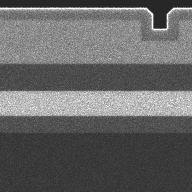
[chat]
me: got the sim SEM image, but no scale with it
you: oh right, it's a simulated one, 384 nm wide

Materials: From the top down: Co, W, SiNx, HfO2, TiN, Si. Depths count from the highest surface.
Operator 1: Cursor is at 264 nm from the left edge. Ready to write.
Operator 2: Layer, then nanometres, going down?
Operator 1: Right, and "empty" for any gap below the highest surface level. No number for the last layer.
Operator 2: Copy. Co 24, W 88, SiNx 54, HfO2 50, TiN 34, Si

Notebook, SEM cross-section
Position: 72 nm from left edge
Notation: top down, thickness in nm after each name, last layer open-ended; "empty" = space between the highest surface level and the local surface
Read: Co 24, W 88, SiNx 54, HfO2 50, TiN 34, Si